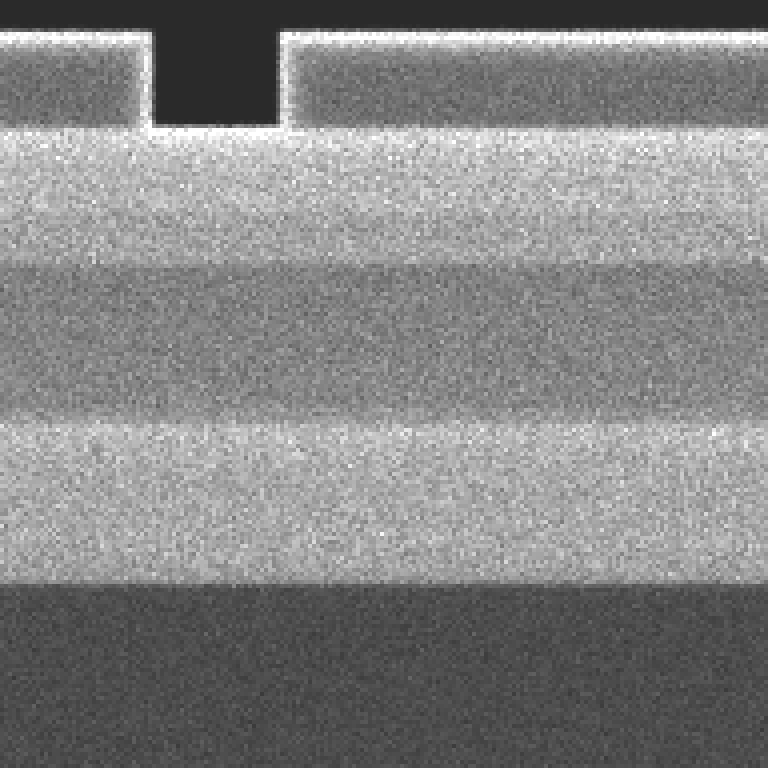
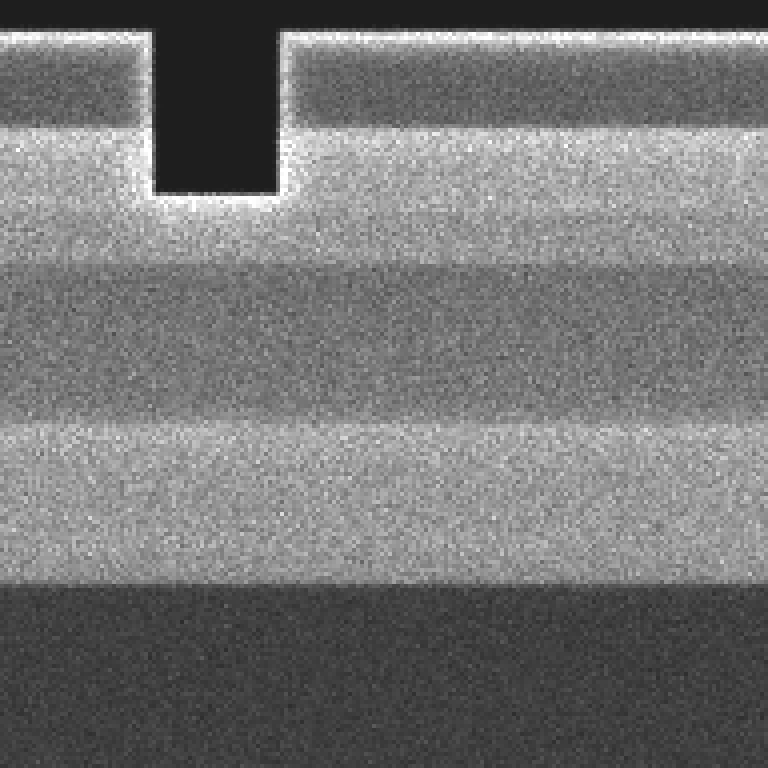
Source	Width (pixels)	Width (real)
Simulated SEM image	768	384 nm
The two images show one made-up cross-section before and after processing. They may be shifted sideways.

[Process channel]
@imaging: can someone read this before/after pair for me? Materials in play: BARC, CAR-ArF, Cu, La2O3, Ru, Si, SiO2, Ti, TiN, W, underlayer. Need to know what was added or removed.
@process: W removed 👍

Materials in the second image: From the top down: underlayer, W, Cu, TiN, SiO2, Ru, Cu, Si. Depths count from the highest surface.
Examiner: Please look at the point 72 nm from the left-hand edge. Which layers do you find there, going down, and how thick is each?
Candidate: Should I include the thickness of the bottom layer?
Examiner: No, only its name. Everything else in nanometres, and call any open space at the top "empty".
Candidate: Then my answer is underlayer 48, W 42, Cu 26, TiN 72, SiO2 8, Ru 64, Cu 16, Si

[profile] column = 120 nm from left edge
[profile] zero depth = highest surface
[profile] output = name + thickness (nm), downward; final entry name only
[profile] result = empty 82, W 8, Cu 26, TiN 72, SiO2 8, Ru 64, Cu 16, Si